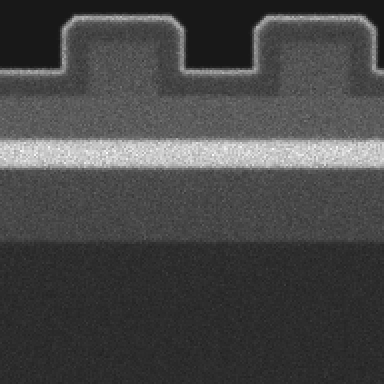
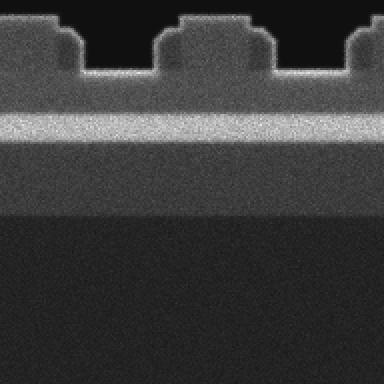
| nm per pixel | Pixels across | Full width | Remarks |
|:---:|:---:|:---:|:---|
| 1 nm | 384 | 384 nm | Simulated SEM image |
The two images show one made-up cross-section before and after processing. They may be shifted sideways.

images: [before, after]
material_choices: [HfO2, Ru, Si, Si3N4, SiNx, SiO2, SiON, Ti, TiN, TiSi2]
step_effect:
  removed: SiNx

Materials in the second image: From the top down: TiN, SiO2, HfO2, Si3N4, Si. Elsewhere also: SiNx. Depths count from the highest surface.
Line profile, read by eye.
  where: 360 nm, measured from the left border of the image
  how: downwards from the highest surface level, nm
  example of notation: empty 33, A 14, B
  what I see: empty 12, SiNx 42, SiO2 44, HfO2 28, Si3N4 74, Si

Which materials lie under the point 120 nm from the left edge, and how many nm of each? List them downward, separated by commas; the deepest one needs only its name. empty 54, SiO2 44, HfO2 28, Si3N4 74, Si